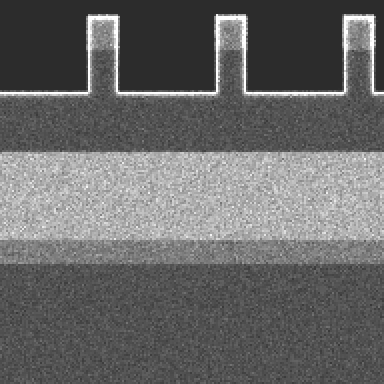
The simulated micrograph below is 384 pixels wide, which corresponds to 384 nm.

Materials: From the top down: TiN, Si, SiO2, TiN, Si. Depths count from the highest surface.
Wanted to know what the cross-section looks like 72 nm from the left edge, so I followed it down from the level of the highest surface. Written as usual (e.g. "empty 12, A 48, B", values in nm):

empty 76, Si 60, SiO2 88, TiN 24, Si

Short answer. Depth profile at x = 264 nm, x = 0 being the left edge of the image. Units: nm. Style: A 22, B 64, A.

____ empty 76, Si 60, SiO2 88, TiN 24, Si